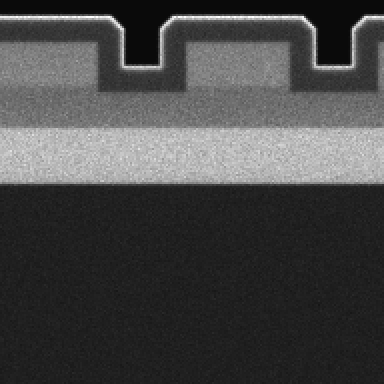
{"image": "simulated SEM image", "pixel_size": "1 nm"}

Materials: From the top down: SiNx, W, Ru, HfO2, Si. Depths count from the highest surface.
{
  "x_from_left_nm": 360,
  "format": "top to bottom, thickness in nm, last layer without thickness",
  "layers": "empty 4, SiNx 72, Ru 36, HfO2 56, Si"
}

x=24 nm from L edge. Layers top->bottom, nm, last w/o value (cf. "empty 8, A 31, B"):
SiNx 26, W 44, Ru 42, HfO2 56, Si